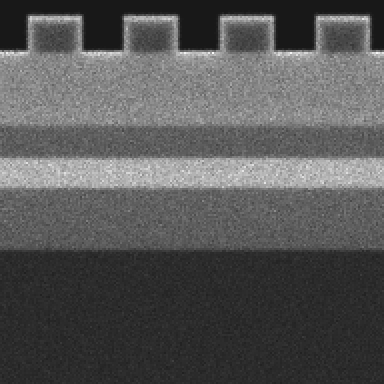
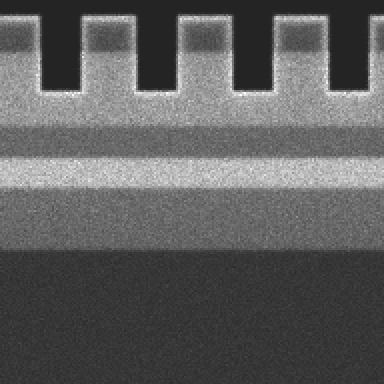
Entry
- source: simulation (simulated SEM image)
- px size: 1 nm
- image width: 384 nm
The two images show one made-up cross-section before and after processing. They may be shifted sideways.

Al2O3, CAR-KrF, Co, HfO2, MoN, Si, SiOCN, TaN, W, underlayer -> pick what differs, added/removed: W removed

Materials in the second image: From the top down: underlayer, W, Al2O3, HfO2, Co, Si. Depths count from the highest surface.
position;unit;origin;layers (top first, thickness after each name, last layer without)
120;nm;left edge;underlayer 36, W 74, Al2O3 32, HfO2 30, Co 62, Si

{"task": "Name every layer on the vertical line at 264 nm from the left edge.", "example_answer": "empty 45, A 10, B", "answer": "empty 76, W 34, Al2O3 32, HfO2 30, Co 62, Si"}